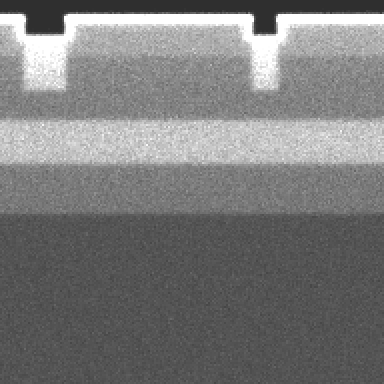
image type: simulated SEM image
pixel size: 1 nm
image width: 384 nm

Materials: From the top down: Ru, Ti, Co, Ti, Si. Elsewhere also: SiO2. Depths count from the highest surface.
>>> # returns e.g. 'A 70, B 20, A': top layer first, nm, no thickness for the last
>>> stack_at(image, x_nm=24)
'empty 20, Ru 54, Ti 30, Co 44, Ti 50, Si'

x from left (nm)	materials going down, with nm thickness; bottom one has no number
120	SiO2 40, Ti 64, Co 44, Ti 50, Si